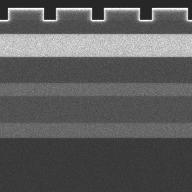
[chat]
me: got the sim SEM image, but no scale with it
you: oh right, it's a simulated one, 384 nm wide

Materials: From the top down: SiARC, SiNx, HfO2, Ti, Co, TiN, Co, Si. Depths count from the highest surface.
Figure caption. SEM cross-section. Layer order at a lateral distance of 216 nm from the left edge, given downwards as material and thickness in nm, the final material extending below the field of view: SiARC 24, SiNx 28, HfO2 46, Ti 52, Co 26, TiN 54, Co 30, Si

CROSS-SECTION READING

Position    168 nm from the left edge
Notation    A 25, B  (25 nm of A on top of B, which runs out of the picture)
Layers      SiARC 24, SiNx 28, HfO2 46, Ti 52, Co 26, TiN 54, Co 30, Si